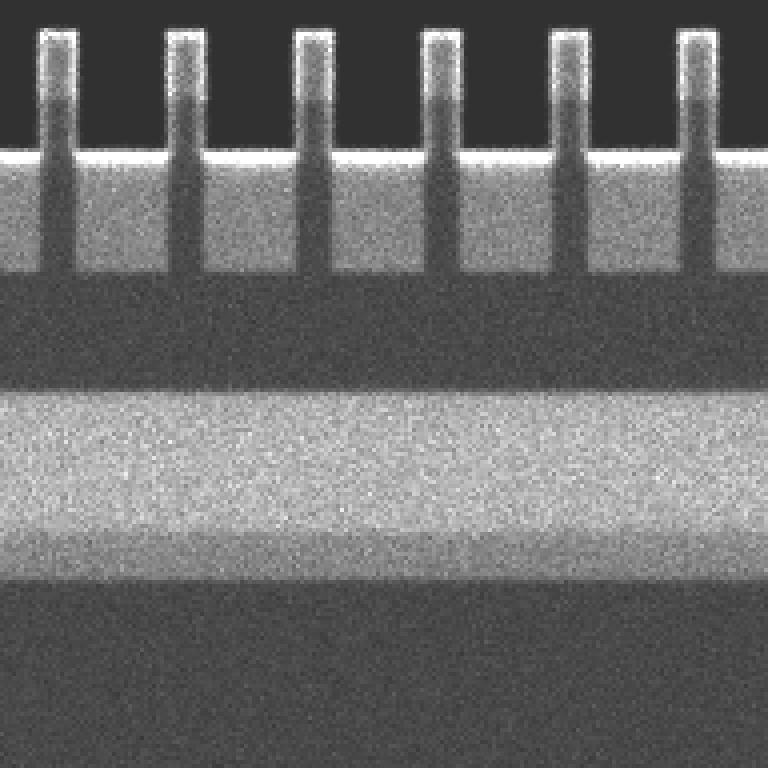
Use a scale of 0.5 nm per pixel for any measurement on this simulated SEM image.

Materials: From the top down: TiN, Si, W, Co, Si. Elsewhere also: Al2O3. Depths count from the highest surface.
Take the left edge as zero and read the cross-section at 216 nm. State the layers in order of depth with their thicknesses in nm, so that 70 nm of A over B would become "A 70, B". TiN 34, Si 146, W 70, Co 24, Si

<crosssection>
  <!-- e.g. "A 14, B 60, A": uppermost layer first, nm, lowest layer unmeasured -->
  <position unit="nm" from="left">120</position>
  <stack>empty 60, Al2O3 60, Si 60, W 70, Co 24, Si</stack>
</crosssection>